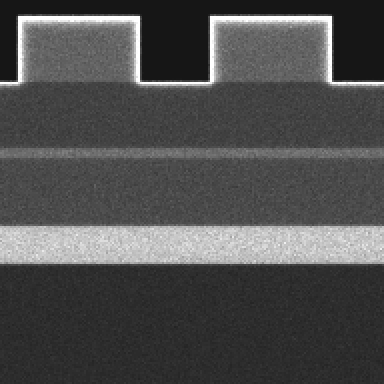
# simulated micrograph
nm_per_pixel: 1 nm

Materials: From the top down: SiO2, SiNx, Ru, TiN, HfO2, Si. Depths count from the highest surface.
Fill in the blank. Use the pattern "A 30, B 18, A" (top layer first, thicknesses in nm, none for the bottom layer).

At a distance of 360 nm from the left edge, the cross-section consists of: empty 66, SiNx 66, Ru 10, TiN 68, HfO2 38, Si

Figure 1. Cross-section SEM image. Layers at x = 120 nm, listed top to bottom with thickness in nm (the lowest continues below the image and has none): SiO2 66, SiNx 66, Ru 10, TiN 68, HfO2 38, Si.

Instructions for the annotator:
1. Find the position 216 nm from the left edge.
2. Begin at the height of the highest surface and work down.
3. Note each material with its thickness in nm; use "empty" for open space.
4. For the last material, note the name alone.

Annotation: SiO2 66, SiNx 66, Ru 10, TiN 68, HfO2 38, Si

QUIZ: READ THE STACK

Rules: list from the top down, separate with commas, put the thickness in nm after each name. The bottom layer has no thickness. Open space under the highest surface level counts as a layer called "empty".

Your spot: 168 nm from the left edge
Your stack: empty 66, SiNx 66, Ru 10, TiN 68, HfO2 38, Si